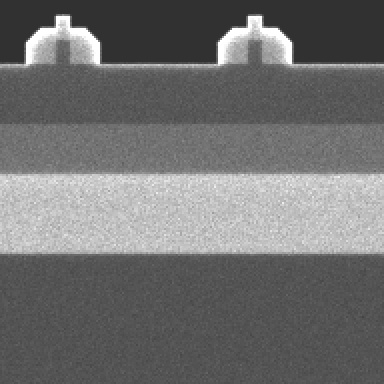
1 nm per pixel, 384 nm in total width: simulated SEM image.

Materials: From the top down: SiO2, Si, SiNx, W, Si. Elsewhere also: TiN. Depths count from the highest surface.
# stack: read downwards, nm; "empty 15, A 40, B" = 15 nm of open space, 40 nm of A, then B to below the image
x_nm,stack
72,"empty 12, SiO2 36, Si 60, SiNx 50, W 80, Si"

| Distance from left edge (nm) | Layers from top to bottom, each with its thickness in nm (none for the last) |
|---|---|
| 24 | empty 48, Si 60, SiNx 50, W 80, Si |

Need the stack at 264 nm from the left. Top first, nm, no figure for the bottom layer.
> empty 12, SiO2 36, Si 60, SiNx 50, W 80, Si